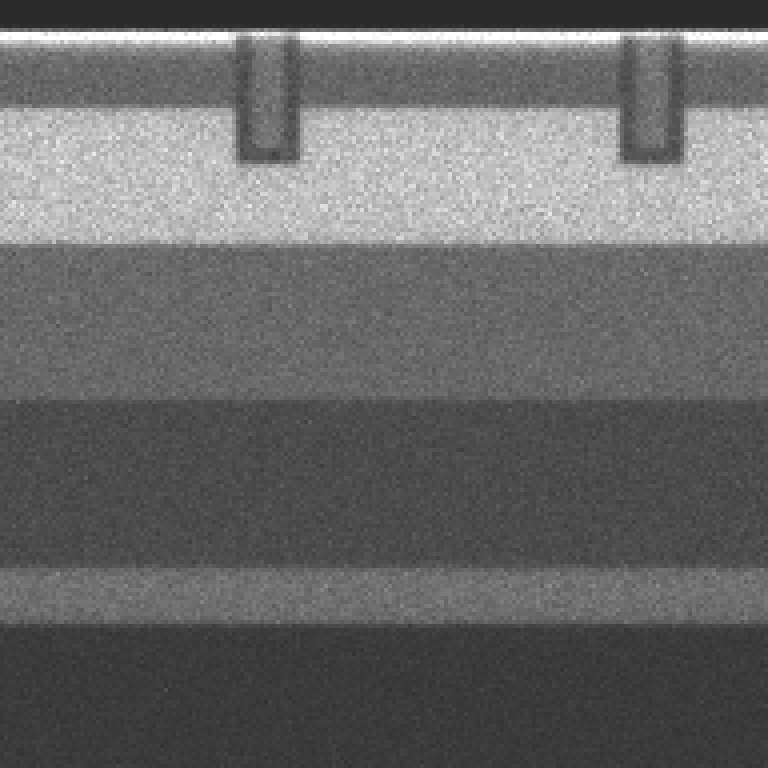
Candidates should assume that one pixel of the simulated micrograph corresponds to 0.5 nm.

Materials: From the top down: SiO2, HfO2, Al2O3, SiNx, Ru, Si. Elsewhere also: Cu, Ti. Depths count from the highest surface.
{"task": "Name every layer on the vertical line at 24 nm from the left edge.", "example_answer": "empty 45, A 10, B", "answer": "SiO2 38, HfO2 68, Al2O3 78, SiNx 84, Ru 28, Si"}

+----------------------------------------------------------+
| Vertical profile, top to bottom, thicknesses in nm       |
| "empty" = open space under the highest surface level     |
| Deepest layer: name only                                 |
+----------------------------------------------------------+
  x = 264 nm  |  SiO2 38, HfO2 68, Al2O3 78, SiNx 84, Ru 28, Si